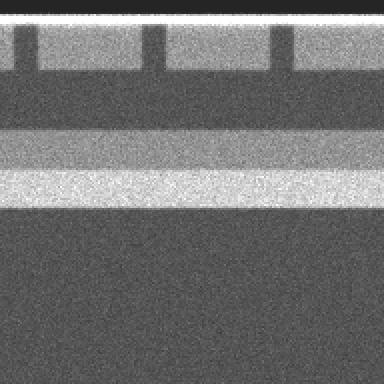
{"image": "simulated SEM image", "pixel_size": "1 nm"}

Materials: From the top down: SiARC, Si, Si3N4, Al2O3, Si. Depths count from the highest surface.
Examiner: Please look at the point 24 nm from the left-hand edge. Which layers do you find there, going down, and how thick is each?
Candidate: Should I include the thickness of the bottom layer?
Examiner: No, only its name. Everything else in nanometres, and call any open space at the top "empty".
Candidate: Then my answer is SiARC 8, Si 106, Si3N4 40, Al2O3 38, Si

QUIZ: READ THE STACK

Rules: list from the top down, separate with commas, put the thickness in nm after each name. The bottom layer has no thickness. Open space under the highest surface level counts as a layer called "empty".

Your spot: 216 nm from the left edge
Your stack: SiARC 54, Si 60, Si3N4 40, Al2O3 38, Si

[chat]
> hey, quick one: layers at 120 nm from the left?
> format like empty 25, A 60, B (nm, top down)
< SiARC 54, Si 60, Si3N4 40, Al2O3 38, Si